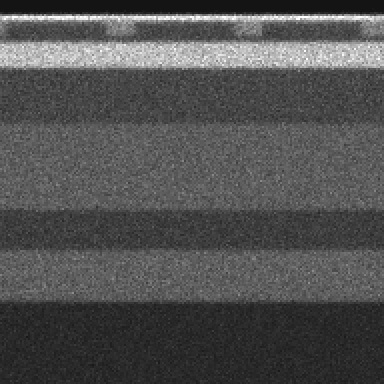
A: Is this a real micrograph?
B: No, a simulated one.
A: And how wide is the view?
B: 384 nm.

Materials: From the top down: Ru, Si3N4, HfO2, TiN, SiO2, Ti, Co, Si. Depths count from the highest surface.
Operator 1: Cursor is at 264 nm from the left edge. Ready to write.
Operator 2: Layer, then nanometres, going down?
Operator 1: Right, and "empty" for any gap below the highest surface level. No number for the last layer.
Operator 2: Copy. Si3N4 26, HfO2 26, TiN 56, SiO2 86, Ti 40, Co 52, Si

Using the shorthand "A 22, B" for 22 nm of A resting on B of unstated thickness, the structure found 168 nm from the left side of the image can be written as Si3N4 26, HfO2 26, TiN 56, SiO2 86, Ti 40, Co 52, Si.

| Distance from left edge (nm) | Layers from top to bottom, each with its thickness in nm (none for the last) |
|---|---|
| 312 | Si3N4 26, HfO2 26, TiN 56, SiO2 86, Ti 40, Co 52, Si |